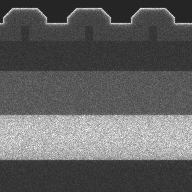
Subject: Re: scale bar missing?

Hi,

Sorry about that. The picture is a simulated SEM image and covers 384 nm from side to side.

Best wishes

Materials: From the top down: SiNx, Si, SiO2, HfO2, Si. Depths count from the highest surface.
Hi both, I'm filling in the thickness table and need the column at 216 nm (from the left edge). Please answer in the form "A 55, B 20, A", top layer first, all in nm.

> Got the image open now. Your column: empty 14, SiNx 52, Si 60, SiO2 88, HfO2 90, Si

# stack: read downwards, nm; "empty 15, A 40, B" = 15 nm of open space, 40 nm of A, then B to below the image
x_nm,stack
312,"SiNx 36, Si 90, SiO2 88, HfO2 90, Si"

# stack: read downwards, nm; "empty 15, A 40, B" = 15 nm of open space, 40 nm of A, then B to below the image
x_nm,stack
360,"empty 30, SiNx 36, Si 60, SiO2 88, HfO2 90, Si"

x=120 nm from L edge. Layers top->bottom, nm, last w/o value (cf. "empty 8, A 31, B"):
empty 30, SiNx 36, Si 60, SiO2 88, HfO2 90, Si